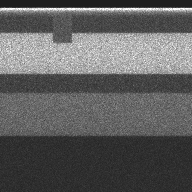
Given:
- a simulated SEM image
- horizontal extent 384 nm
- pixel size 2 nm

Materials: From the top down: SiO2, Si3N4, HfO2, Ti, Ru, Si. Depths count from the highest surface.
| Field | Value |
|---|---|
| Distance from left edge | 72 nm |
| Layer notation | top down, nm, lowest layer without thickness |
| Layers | SiO2 14, Si3N4 36, HfO2 82, Ti 38, Ru 86, Si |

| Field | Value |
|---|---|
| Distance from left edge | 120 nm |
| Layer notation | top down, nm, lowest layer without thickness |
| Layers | SiO2 70, HfO2 62, Ti 38, Ru 86, Si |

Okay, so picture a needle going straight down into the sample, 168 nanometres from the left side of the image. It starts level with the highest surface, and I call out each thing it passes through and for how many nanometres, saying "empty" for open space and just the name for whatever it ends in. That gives SiO2 14, Si3N4 36, HfO2 82, Ti 38, Ru 86, Si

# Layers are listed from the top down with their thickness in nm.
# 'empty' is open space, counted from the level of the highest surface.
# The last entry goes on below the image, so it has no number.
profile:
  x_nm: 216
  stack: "SiO2 14, Si3N4 36, HfO2 82, Ti 38, Ru 86, Si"